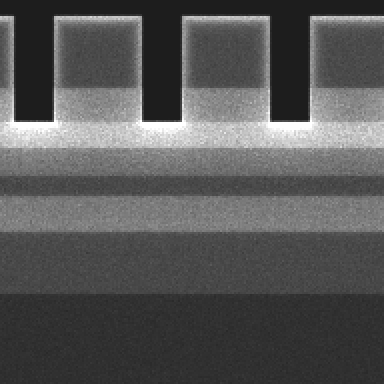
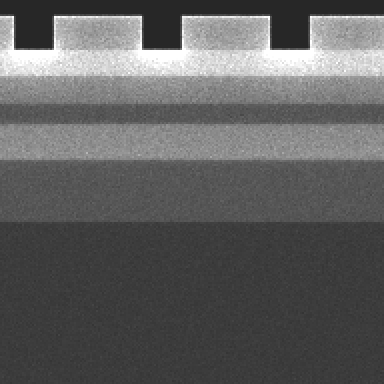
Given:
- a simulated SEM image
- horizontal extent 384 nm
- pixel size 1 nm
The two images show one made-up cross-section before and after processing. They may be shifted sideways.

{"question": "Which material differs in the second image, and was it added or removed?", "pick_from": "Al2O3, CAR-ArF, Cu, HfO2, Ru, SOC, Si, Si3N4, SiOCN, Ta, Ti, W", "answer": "SOC, removed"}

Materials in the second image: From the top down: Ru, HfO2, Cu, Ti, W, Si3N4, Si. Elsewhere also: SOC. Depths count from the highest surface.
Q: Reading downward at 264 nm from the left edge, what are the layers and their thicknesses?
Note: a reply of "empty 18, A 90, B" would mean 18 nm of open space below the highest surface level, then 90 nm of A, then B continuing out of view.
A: Ru 34, HfO2 26, Cu 28, Ti 20, W 36, Si3N4 62, Si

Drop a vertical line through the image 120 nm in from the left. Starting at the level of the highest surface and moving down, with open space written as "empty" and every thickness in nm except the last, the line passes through Ru 34, HfO2 26, Cu 28, Ti 20, W 36, Si3N4 62, Si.